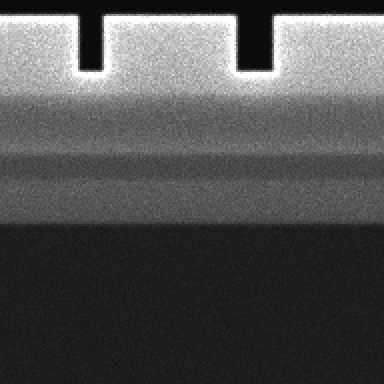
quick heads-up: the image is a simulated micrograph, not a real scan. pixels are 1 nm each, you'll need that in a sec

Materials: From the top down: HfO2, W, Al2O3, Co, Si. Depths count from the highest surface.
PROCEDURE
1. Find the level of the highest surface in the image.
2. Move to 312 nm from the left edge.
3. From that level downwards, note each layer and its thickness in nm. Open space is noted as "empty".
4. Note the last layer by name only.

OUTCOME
HfO2 78, W 60, Al2O3 26, Co 44, Si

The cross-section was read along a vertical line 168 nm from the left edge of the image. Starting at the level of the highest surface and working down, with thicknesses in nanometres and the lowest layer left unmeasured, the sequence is HfO2 78, W 60, Al2O3 26, Co 44, Si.